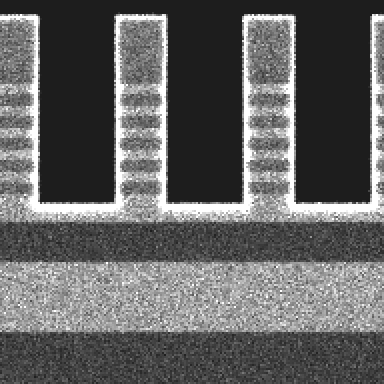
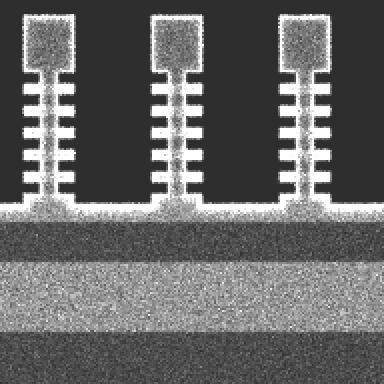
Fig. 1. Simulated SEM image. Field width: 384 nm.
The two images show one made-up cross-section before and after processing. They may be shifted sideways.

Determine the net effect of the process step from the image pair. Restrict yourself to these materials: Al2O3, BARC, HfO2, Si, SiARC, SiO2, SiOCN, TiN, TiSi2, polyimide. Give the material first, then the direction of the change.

SiOCN: removed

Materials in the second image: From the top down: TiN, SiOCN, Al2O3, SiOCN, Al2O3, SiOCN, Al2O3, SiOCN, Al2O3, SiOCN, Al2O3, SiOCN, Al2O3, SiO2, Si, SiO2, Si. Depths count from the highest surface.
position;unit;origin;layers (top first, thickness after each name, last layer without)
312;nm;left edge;TiN 56, SiOCN 12, Al2O3 10, SiOCN 12, Al2O3 10, SiOCN 12, Al2O3 10, SiOCN 12, Al2O3 10, SiOCN 12, Al2O3 10, SiOCN 12, Al2O3 10, SiO2 18, Si 40, SiO2 70, Si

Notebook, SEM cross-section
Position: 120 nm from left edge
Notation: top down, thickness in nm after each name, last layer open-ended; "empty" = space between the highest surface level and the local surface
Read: empty 188, SiO2 18, Si 40, SiO2 70, Si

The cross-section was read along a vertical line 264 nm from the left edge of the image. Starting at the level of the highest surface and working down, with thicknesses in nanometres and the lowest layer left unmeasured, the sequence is empty 188, SiO2 18, Si 40, SiO2 70, Si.